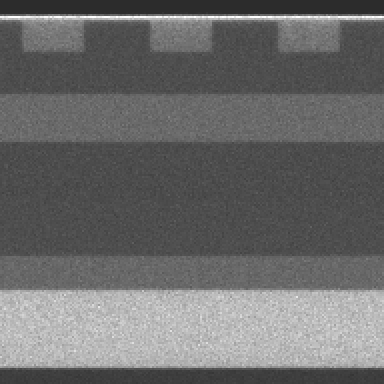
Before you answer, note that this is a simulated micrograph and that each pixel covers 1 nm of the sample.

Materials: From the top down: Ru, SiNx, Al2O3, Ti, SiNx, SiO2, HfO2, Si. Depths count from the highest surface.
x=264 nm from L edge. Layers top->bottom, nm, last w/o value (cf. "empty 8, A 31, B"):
SiNx 78, Al2O3 48, Ti 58, SiNx 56, SiO2 34, HfO2 78, Si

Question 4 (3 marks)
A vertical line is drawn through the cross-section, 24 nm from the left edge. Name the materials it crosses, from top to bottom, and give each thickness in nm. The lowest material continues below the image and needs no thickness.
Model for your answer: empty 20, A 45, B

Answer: Ru 36, SiNx 42, Al2O3 48, Ti 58, SiNx 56, SiO2 34, HfO2 78, Si